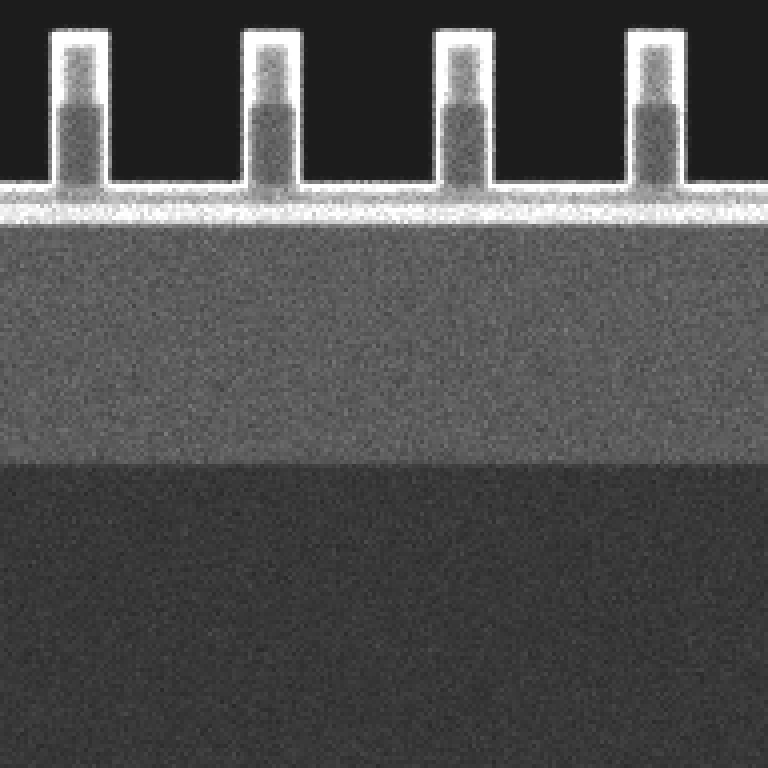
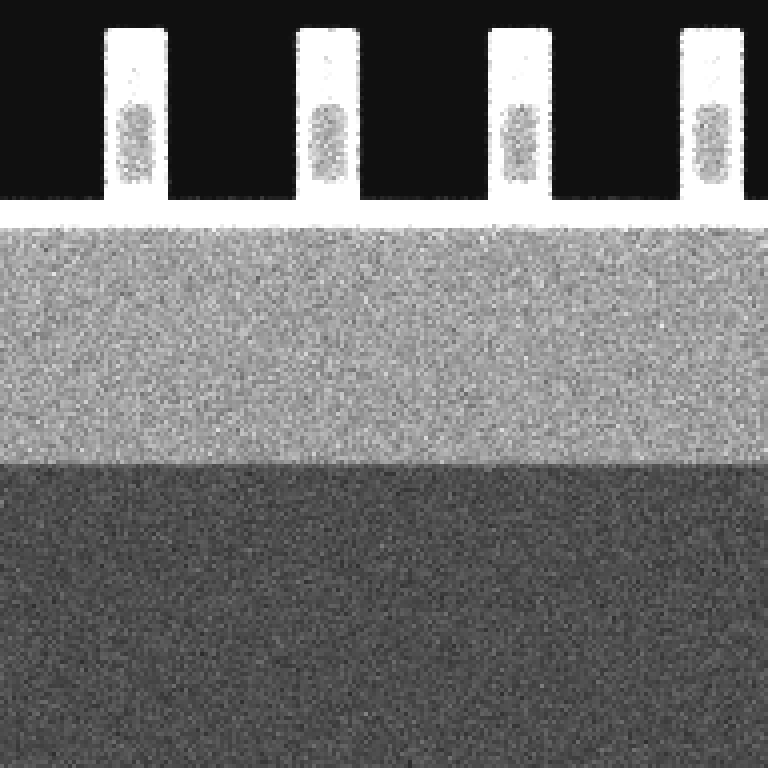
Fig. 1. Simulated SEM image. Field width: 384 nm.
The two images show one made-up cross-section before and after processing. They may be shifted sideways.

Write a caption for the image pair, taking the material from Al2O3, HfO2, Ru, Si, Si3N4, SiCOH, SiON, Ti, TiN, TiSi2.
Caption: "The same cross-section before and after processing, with Ru removed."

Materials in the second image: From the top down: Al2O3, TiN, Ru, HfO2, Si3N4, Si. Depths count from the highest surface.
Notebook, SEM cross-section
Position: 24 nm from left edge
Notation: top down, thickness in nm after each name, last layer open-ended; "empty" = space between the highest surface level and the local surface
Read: empty 86, HfO2 10, Si3N4 120, Si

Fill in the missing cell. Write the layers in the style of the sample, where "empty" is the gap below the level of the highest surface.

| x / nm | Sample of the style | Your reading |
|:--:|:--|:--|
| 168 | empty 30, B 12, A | Al2O3 36, TiN 40, Ru 10, HfO2 10, Si3N4 120, Si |